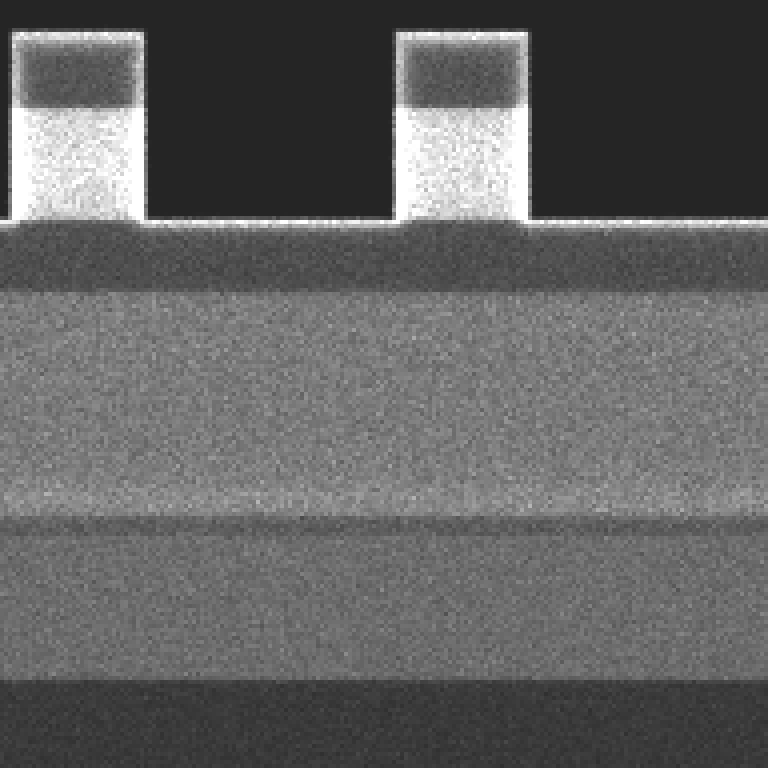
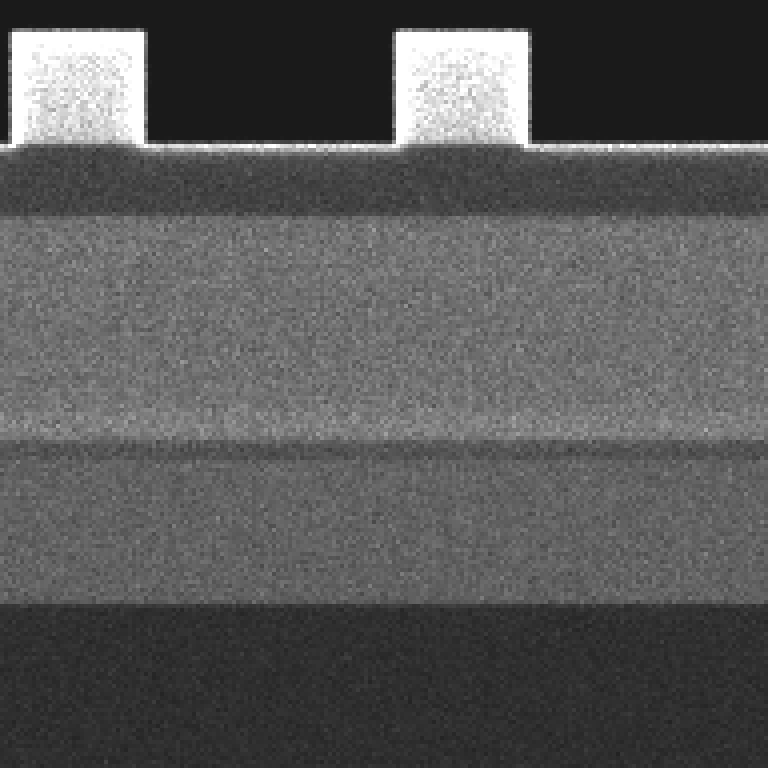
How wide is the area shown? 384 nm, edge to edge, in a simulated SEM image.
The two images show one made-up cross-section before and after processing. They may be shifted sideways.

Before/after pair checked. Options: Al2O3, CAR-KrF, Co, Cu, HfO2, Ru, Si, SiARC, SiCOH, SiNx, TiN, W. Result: removed SiARC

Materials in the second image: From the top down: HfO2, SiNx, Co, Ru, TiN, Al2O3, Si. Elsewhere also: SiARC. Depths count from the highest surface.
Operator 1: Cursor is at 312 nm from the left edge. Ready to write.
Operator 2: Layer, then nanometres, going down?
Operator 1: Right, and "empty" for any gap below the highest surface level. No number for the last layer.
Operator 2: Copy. empty 56, SiNx 36, Co 98, Ru 14, TiN 10, Al2O3 72, Si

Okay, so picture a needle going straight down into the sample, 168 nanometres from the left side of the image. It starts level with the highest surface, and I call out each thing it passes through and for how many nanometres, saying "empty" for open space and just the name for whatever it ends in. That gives empty 56, SiNx 36, Co 98, Ru 14, TiN 10, Al2O3 72, Si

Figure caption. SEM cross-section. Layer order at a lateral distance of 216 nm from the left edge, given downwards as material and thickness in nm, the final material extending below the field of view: HfO2 56, SiNx 36, Co 98, Ru 14, TiN 10, Al2O3 72, Si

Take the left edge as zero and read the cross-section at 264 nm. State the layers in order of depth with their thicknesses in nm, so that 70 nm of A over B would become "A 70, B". empty 56, SiNx 36, Co 98, Ru 14, TiN 10, Al2O3 72, Si